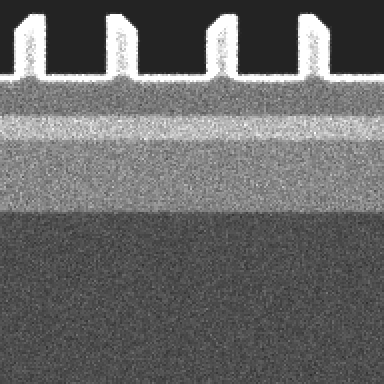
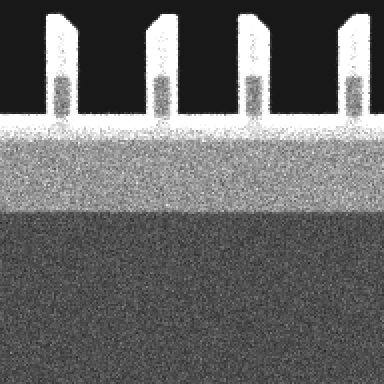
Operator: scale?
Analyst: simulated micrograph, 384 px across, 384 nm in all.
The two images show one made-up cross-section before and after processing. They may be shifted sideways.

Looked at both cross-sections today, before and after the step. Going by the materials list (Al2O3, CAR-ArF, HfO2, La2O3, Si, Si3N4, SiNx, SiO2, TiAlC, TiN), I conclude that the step removed SiNx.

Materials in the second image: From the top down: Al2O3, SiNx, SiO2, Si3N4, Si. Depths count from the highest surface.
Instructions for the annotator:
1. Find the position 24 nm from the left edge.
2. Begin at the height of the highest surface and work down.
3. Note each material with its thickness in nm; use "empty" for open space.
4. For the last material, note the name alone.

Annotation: empty 100, SiO2 24, Si3N4 72, Si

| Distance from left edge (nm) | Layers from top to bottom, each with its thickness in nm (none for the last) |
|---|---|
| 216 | empty 100, SiO2 24, Si3N4 72, Si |